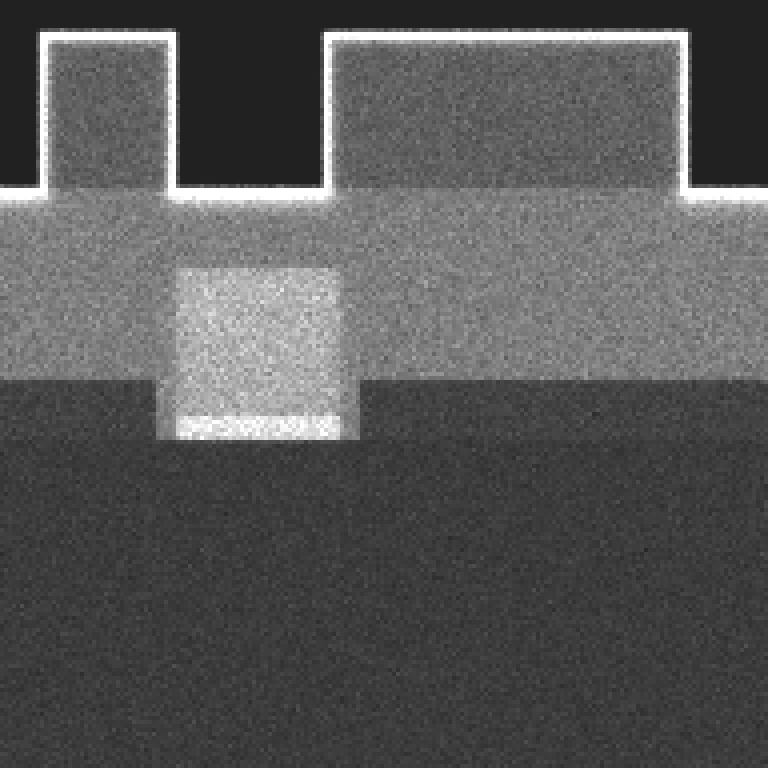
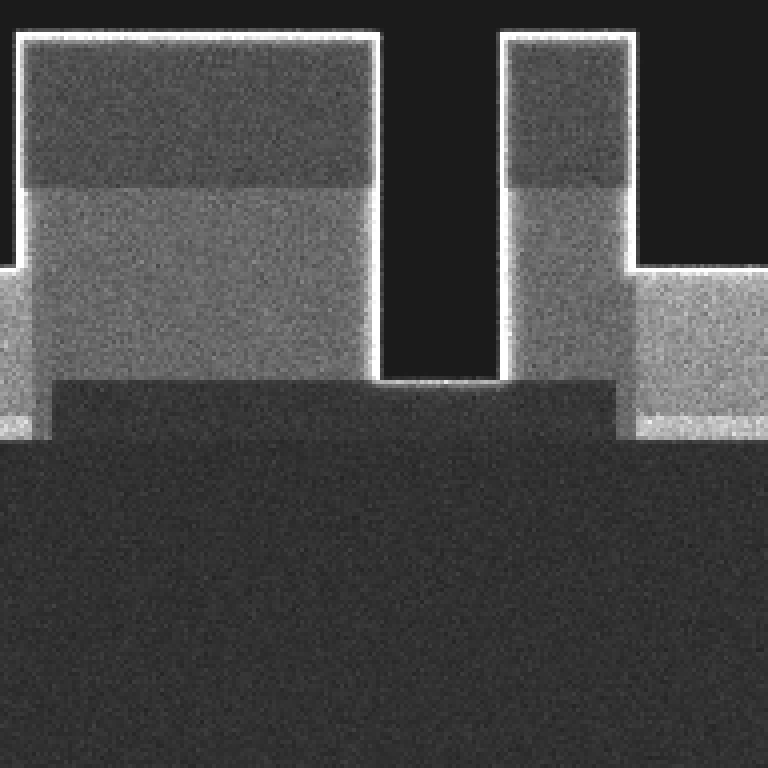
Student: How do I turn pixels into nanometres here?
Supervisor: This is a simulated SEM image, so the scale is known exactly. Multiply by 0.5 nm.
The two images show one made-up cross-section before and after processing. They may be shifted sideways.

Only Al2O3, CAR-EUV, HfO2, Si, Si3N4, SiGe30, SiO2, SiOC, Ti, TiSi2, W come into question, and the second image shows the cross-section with SiO2 removed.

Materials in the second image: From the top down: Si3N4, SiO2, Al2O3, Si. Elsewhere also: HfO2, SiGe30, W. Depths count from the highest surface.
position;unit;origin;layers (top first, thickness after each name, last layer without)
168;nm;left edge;Si3N4 78, SiO2 96, SiGe30 30, Si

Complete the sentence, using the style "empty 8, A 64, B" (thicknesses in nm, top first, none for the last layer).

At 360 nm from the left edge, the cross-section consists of empty 118, W 74, HfO2 12, Si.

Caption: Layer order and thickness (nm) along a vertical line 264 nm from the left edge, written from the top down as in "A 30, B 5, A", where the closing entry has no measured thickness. Si3N4 78, SiO2 96, SiGe30 30, Si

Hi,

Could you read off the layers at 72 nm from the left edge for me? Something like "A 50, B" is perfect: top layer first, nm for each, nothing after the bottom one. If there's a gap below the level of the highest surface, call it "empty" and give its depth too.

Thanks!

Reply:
Si3N4 78, SiO2 96, SiGe30 30, Si